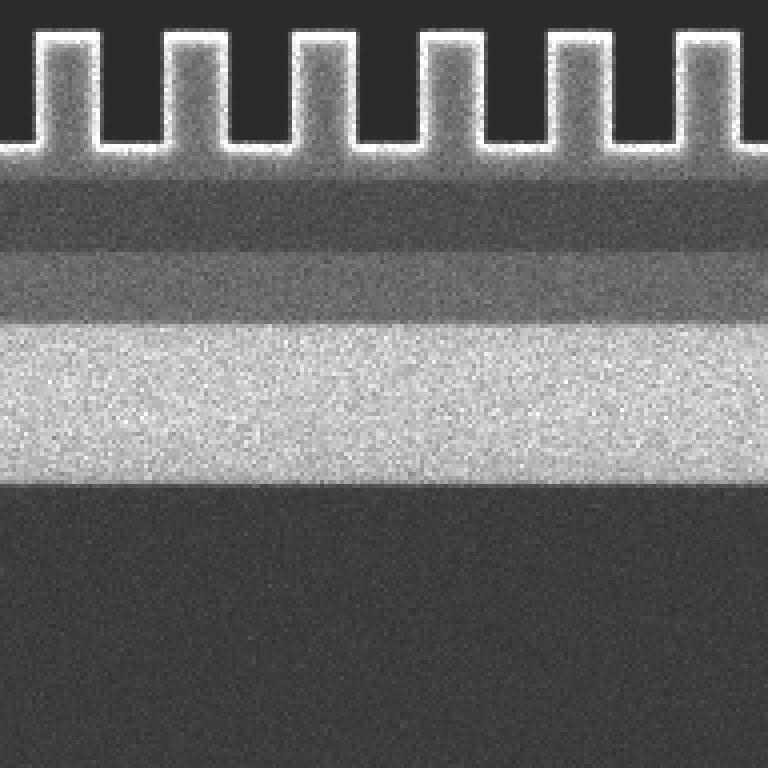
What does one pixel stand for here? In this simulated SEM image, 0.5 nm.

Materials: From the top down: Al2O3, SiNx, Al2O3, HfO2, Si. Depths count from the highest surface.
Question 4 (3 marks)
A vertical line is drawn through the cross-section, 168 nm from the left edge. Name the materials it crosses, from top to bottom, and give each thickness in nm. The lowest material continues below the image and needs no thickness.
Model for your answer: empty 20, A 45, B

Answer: Al2O3 74, SiNx 36, Al2O3 36, HfO2 80, Si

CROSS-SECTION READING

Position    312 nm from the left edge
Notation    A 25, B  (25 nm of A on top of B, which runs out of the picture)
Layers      empty 56, Al2O3 18, SiNx 36, Al2O3 36, HfO2 80, Si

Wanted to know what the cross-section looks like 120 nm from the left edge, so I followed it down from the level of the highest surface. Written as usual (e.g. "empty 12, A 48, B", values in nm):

empty 56, Al2O3 18, SiNx 36, Al2O3 36, HfO2 80, Si